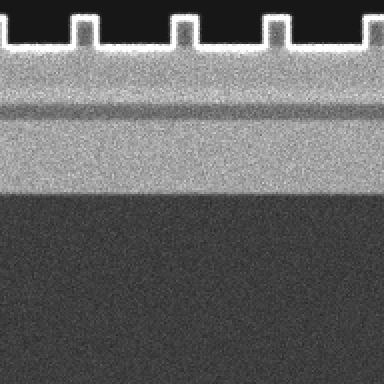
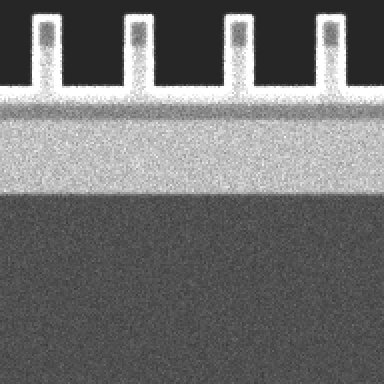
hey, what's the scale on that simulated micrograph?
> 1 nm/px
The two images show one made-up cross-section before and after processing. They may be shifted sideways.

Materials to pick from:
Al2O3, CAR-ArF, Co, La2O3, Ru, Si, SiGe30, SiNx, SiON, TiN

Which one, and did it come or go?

Co - removed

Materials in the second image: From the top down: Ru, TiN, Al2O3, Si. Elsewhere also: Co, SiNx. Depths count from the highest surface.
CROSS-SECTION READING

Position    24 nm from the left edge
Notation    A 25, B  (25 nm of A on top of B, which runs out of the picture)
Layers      empty 72, Ru 16, TiN 16, Al2O3 74, Si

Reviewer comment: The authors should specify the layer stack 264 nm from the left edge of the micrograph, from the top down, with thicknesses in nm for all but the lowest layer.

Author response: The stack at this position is empty 72, Ru 16, TiN 16, Al2O3 74, Si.